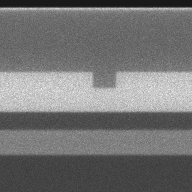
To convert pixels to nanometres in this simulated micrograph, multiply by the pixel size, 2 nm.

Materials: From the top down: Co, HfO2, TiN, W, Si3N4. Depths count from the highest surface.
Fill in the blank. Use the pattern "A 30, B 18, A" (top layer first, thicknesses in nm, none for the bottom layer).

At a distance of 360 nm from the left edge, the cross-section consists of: Co 128, HfO2 80, TiN 36, W 50, Si3N4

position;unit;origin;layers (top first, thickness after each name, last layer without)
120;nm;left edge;Co 128, HfO2 80, TiN 36, W 50, Si3N4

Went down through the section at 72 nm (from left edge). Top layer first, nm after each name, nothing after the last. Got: Co 128, HfO2 80, TiN 36, W 50, Si3N4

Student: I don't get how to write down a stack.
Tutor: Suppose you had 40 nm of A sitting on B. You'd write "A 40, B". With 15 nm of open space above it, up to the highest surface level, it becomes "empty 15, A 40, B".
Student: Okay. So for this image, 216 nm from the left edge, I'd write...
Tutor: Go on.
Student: Co 160, HfO2 48, TiN 36, W 50, Si3N4